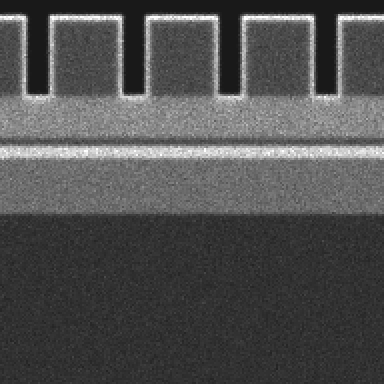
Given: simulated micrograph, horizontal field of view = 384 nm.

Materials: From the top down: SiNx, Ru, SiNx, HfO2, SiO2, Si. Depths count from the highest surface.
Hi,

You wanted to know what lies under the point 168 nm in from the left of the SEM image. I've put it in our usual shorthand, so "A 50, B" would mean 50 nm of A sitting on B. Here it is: SiNx 80, Ru 42, SiNx 8, HfO2 12, SiO2 56, Si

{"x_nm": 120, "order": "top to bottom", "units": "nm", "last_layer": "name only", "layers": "SiNx 80, Ru 42, SiNx 8, HfO2 12, SiO2 56, Si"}